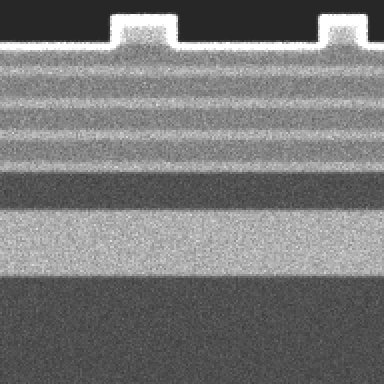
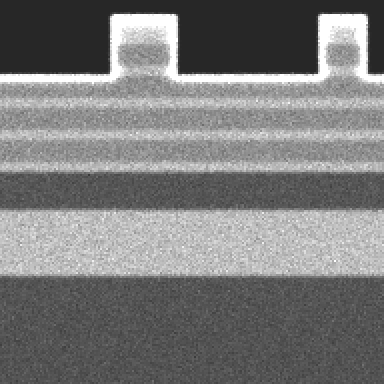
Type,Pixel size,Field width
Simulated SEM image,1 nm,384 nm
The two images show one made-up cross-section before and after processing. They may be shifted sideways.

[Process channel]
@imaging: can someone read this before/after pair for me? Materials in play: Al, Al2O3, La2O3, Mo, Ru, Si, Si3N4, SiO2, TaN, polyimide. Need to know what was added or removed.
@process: Si3N4 and SiO2 removed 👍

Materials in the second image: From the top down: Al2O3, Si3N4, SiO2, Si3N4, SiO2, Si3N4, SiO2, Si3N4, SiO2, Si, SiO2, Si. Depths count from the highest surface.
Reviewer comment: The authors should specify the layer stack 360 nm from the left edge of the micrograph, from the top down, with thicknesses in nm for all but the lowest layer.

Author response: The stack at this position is Al2O3 28, Si3N4 22, SiO2 10, Si3N4 22, SiO2 10, Si3N4 22, SiO2 10, Si3N4 22, SiO2 10, Si 38, SiO2 66, Si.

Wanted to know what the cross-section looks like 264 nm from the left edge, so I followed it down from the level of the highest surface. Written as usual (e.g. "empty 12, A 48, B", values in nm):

empty 60, Si3N4 22, SiO2 10, Si3N4 22, SiO2 10, Si3N4 22, SiO2 10, Si 38, SiO2 66, Si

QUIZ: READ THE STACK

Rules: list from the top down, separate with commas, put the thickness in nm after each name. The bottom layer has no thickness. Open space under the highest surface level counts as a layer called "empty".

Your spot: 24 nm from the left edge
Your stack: empty 60, Si3N4 22, SiO2 10, Si3N4 22, SiO2 10, Si3N4 22, SiO2 10, Si 38, SiO2 66, Si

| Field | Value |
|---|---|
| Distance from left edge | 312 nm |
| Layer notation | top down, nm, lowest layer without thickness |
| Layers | empty 60, Si3N4 22, SiO2 10, Si3N4 22, SiO2 10, Si3N4 22, SiO2 10, Si 38, SiO2 66, Si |